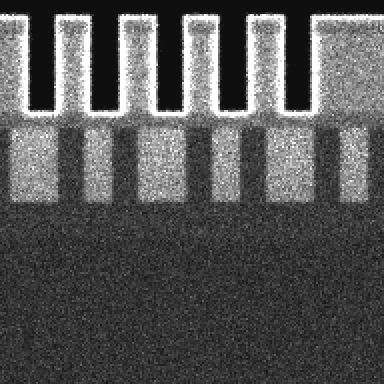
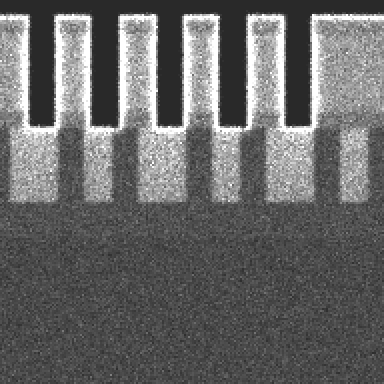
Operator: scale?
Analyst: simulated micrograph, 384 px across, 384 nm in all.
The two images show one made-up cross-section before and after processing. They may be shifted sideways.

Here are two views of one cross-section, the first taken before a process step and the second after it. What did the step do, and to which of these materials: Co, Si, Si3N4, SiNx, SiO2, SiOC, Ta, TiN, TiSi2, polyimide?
It removed Si3N4.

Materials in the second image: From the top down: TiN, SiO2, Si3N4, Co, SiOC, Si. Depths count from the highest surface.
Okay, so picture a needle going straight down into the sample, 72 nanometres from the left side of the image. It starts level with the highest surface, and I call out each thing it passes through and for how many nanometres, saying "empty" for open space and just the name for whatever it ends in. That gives TiN 18, SiO2 78, Si3N4 16, SiOC 110, Si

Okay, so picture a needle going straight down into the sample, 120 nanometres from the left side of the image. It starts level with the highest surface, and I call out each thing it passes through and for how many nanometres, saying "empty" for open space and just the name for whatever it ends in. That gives TiN 18, SiO2 78, Si3N4 16, SiOC 110, Si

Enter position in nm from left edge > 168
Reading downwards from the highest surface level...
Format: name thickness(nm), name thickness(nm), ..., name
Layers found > empty 112, Co 74, SiOC 36, Si